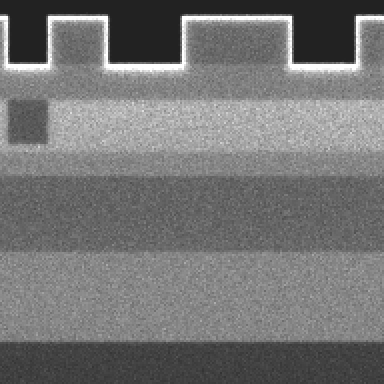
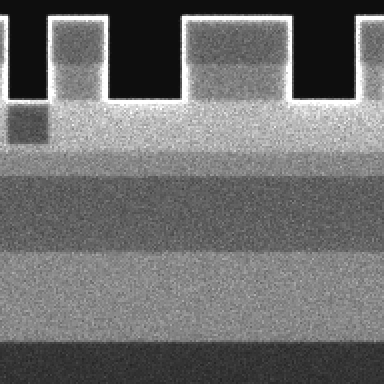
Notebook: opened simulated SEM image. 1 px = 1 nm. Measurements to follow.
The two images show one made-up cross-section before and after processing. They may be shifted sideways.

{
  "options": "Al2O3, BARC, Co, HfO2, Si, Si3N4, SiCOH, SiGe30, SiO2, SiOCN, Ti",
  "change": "removed",
  "material": "SiO2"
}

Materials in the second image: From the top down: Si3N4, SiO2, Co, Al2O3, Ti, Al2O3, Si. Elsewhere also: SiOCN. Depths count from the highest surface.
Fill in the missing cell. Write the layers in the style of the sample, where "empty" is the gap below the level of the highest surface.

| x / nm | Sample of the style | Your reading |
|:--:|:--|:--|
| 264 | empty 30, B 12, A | Si3N4 48, SiO2 36, Co 52, Al2O3 24, Ti 76, Al2O3 90, Si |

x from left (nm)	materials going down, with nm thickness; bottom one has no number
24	empty 84, SiOCN 44, Co 8, Al2O3 24, Ti 76, Al2O3 90, Si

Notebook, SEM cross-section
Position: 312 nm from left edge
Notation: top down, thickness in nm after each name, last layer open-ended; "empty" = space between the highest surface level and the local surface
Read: empty 84, Co 52, Al2O3 24, Ti 76, Al2O3 90, Si